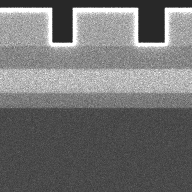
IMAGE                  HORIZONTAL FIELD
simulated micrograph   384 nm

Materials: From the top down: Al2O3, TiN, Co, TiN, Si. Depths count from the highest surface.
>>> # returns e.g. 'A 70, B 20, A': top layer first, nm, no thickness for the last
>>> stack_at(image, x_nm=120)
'empty 70, Al2O3 6, TiN 46, Co 48, TiN 30, Si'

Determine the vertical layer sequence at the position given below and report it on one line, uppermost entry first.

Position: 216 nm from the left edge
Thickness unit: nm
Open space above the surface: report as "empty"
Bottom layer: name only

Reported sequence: Al2O3 76, TiN 46, Co 48, TiN 30, Si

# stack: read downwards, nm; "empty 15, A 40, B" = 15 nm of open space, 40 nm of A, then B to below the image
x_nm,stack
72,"Al2O3 76, TiN 46, Co 48, TiN 30, Si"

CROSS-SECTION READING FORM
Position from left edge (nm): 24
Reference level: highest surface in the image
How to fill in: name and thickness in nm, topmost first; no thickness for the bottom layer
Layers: Al2O3 76, TiN 46, Co 48, TiN 30, Si